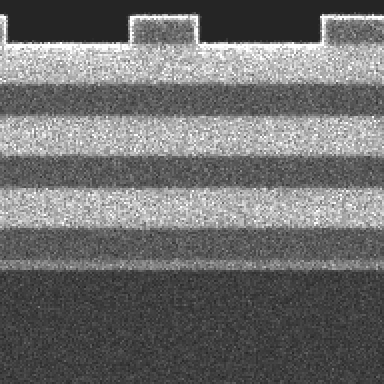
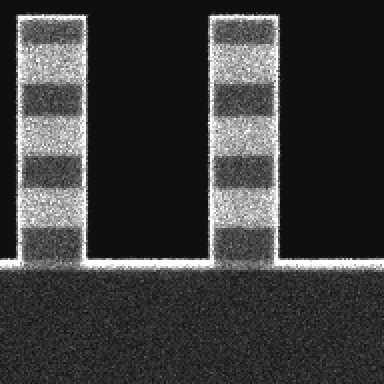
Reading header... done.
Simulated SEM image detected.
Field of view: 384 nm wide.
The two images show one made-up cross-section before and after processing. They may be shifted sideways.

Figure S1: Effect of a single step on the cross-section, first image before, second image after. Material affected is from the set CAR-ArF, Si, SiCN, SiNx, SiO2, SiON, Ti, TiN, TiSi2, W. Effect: removed SiNx and W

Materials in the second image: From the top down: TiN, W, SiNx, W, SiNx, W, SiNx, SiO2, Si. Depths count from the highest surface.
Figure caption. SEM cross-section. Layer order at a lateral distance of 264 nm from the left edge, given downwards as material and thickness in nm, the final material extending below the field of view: TiN 28, W 40, SiNx 32, W 40, SiNx 32, W 40, SiNx 32, SiO2 10, Si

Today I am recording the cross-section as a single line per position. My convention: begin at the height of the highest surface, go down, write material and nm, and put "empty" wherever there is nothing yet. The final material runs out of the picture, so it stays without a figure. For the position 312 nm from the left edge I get empty 244, SiO2 10, Si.